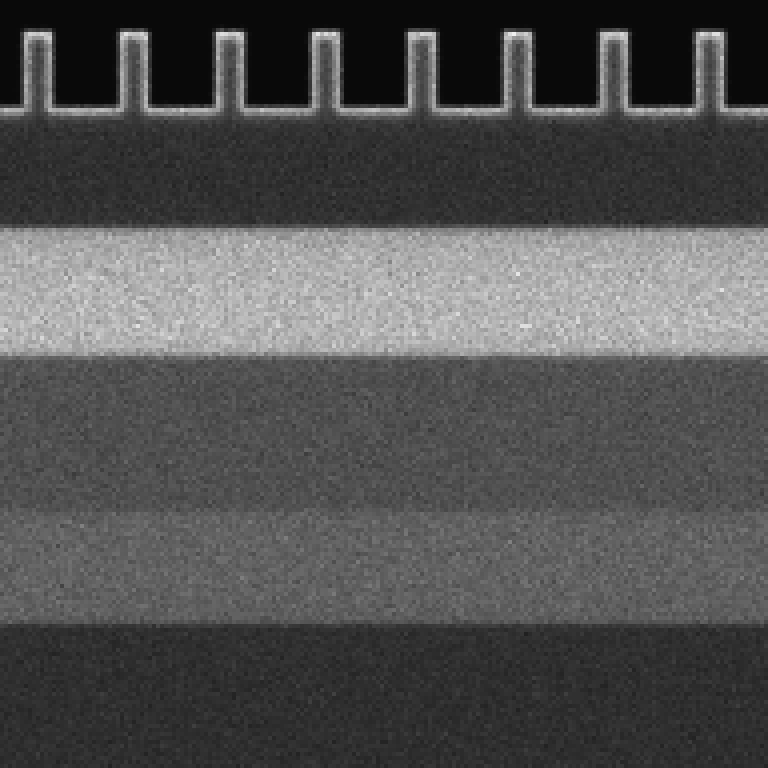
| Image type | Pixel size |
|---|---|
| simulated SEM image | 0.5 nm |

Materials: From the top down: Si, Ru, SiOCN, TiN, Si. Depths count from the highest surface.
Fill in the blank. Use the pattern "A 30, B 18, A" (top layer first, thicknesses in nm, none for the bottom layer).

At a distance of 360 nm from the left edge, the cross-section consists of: Si 98, Ru 64, SiOCN 78, TiN 56, Si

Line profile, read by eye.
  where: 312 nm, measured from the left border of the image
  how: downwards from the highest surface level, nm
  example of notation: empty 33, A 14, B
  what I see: Si 98, Ru 64, SiOCN 78, TiN 56, Si